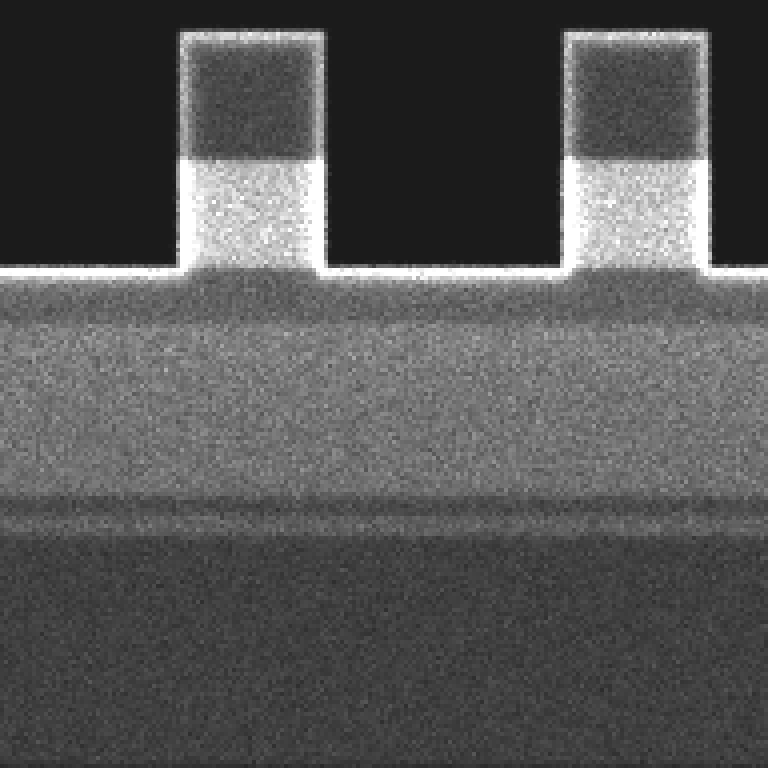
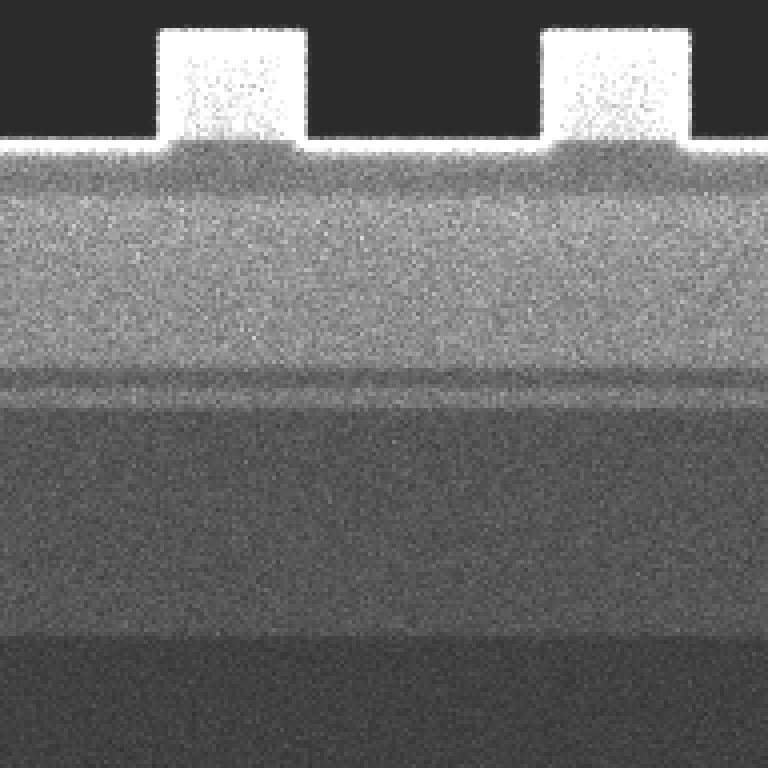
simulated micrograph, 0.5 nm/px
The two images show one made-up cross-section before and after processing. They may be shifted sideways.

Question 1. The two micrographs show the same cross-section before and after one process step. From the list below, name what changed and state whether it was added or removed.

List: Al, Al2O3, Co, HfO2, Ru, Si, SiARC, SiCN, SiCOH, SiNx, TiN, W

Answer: SiARC, removed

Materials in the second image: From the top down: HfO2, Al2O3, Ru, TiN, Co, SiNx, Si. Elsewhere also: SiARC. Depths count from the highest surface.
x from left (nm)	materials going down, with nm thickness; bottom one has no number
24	empty 54, Al2O3 28, Ru 86, TiN 10, Co 10, SiNx 114, Si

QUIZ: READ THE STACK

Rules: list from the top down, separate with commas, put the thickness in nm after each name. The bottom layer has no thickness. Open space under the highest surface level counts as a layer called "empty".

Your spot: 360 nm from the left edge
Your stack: empty 54, Al2O3 28, Ru 86, TiN 10, Co 10, SiNx 114, Si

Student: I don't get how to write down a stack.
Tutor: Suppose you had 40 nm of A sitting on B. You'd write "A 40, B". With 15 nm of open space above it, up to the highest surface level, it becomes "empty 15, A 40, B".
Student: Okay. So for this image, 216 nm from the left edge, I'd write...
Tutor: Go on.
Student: empty 54, Al2O3 28, Ru 86, TiN 10, Co 10, SiNx 114, Si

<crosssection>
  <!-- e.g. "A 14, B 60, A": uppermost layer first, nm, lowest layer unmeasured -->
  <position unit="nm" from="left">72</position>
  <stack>empty 54, Al2O3 28, Ru 86, TiN 10, Co 10, SiNx 114, Si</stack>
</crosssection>